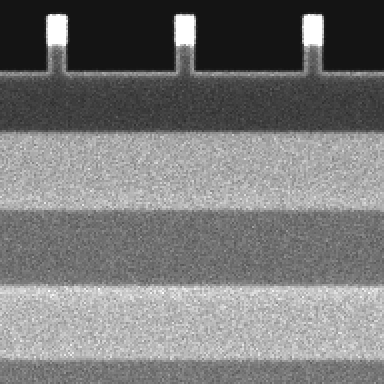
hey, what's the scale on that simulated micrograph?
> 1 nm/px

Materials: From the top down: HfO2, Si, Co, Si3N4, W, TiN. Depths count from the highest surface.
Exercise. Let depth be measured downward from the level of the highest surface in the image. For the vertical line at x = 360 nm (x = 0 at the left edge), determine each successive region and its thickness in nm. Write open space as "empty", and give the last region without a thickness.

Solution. empty 56, Si 60, Co 78, Si3N4 76, W 74, TiN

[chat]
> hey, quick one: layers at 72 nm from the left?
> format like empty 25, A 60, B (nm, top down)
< empty 56, Si 60, Co 78, Si3N4 76, W 74, TiN